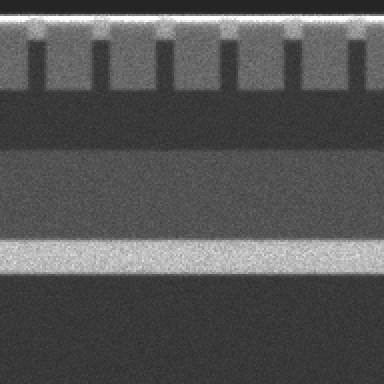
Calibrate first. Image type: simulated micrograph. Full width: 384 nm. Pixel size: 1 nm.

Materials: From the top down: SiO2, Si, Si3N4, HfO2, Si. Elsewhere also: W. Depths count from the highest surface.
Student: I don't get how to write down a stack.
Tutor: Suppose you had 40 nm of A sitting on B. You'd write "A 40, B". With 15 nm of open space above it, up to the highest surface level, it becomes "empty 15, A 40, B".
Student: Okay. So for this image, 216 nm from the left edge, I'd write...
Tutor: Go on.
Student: SiO2 74, Si 60, Si3N4 90, HfO2 34, Si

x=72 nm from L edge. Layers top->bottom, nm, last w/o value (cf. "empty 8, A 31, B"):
SiO2 74, Si 60, Si3N4 90, HfO2 34, Si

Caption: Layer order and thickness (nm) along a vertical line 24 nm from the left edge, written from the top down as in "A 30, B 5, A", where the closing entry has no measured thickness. SiO2 74, Si 60, Si3N4 90, HfO2 34, Si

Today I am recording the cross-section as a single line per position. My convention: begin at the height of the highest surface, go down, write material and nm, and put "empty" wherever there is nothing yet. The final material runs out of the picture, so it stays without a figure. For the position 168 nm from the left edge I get W 24, Si 110, Si3N4 90, HfO2 34, Si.